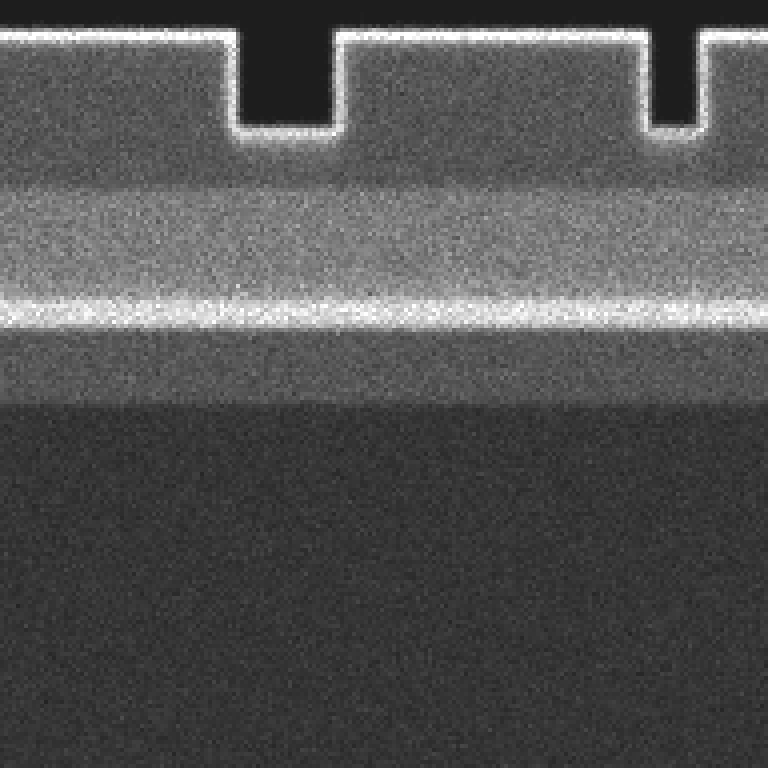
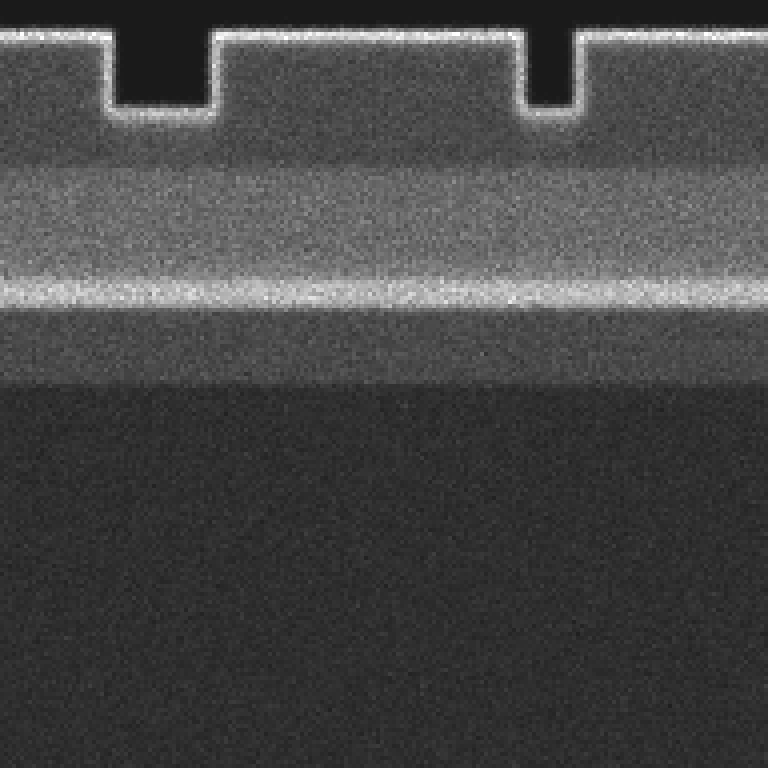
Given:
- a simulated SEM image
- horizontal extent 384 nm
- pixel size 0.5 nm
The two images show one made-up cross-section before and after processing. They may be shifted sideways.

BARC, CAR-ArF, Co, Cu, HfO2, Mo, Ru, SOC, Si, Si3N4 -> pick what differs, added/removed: Si3N4 removed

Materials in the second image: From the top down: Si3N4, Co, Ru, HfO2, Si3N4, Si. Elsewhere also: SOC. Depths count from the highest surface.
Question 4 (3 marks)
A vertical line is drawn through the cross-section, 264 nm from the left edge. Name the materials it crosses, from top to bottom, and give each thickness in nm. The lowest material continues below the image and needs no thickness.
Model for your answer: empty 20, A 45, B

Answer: empty 38, SOC 30, Co 46, Ru 10, HfO2 14, Si3N4 38, Si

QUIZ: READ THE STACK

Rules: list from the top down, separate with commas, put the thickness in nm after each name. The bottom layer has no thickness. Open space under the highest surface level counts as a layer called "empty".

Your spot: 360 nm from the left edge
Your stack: Si3N4 68, Co 46, Ru 10, HfO2 14, Si3N4 38, Si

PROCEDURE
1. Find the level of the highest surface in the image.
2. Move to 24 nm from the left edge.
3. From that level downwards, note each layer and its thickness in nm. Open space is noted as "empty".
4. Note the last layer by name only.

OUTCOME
Si3N4 68, Co 46, Ru 10, HfO2 14, Si3N4 38, Si